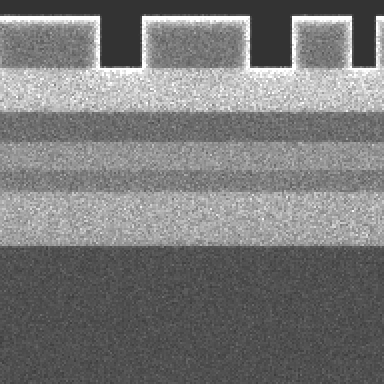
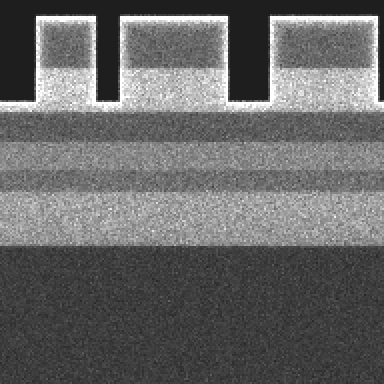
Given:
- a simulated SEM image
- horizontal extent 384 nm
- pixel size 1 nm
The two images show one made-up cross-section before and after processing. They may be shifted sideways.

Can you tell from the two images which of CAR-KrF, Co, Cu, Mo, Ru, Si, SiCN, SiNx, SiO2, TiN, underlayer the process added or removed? Yes, it removed Ru.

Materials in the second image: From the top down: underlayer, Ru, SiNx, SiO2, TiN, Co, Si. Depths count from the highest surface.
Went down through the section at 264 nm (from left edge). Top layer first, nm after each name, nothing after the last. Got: empty 86, Ru 10, SiNx 30, SiO2 28, TiN 22, Co 54, Si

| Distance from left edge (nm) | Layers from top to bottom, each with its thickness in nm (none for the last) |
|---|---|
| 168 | underlayer 52, Ru 44, SiNx 30, SiO2 28, TiN 22, Co 54, Si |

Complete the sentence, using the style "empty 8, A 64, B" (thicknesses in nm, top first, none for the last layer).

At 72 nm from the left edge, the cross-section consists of underlayer 52, Ru 44, SiNx 30, SiO2 28, TiN 22, Co 54, Si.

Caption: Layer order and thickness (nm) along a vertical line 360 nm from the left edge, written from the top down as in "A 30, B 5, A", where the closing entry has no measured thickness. underlayer 52, Ru 44, SiNx 30, SiO2 28, TiN 22, Co 54, Si